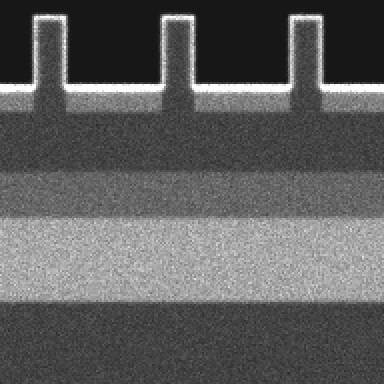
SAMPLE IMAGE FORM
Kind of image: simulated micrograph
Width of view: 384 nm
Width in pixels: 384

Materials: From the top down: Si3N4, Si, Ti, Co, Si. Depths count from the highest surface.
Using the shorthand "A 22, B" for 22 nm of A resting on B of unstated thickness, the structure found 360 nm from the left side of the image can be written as empty 70, Si3N4 26, Si 60, Ti 46, Co 84, Si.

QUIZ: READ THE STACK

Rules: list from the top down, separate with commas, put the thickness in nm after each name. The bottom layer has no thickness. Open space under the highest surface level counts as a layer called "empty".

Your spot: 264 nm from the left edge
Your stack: empty 70, Si3N4 26, Si 60, Ti 46, Co 84, Si